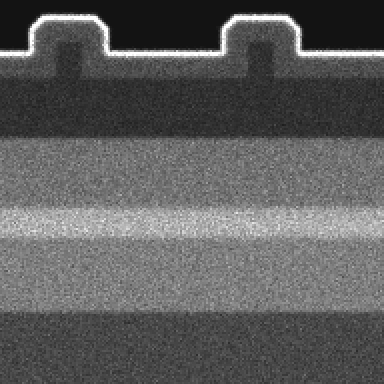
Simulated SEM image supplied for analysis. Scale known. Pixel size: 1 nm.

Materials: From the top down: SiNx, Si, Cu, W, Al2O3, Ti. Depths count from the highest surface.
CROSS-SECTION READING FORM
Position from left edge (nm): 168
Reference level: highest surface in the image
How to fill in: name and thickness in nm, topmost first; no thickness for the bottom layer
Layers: empty 36, SiNx 26, Si 60, Cu 70, W 30, Al2O3 74, Ti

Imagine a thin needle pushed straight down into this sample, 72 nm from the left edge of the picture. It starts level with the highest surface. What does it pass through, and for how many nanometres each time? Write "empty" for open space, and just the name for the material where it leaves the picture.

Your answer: SiNx 26, Si 96, Cu 70, W 30, Al2O3 74, Ti